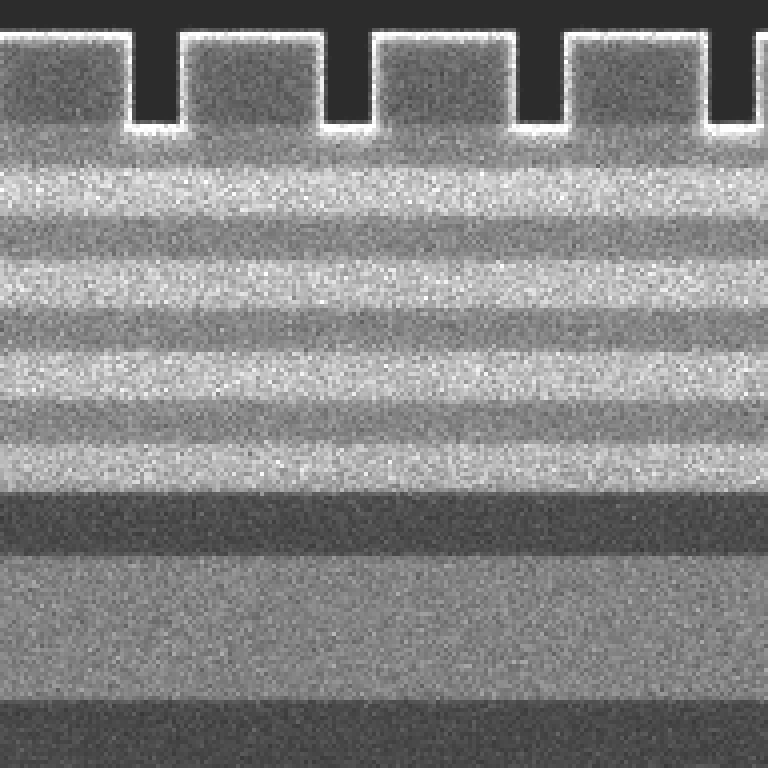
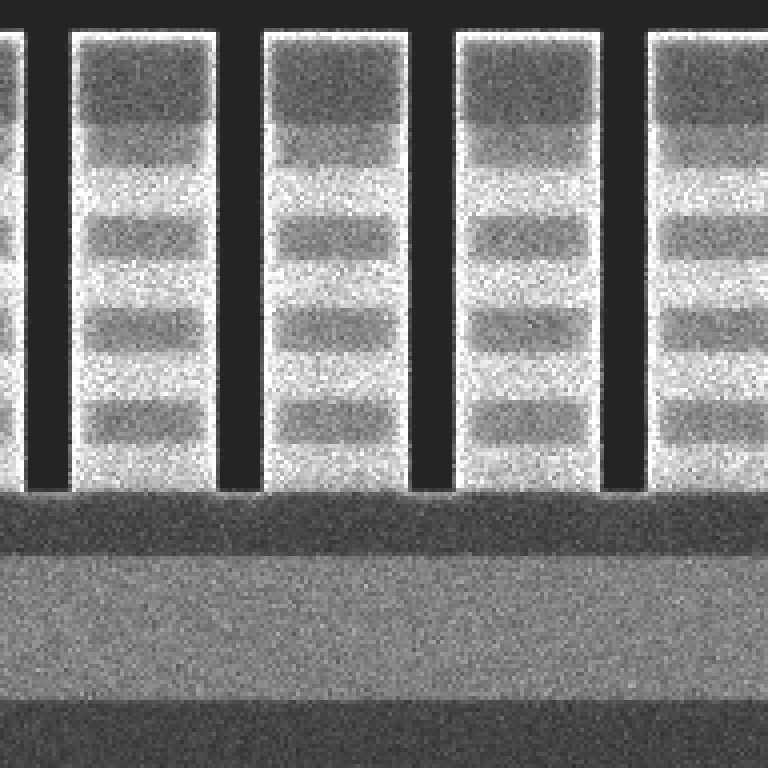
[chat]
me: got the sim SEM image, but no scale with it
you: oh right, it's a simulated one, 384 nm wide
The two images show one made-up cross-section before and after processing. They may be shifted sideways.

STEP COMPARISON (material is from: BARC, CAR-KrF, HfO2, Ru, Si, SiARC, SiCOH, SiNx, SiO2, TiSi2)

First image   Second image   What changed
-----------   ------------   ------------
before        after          Ru and SiO2, removed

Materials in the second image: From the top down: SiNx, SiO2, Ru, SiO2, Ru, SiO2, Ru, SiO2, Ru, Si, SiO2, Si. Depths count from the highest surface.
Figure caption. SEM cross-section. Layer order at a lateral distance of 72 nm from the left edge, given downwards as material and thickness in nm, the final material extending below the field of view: SiNx 46, SiO2 22, Ru 24, SiO2 22, Ru 24, SiO2 22, Ru 24, SiO2 22, Ru 24, Si 32, SiO2 72, Si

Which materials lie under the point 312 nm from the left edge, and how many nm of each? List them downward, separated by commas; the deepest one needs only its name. empty 230, Si 32, SiO2 72, Si